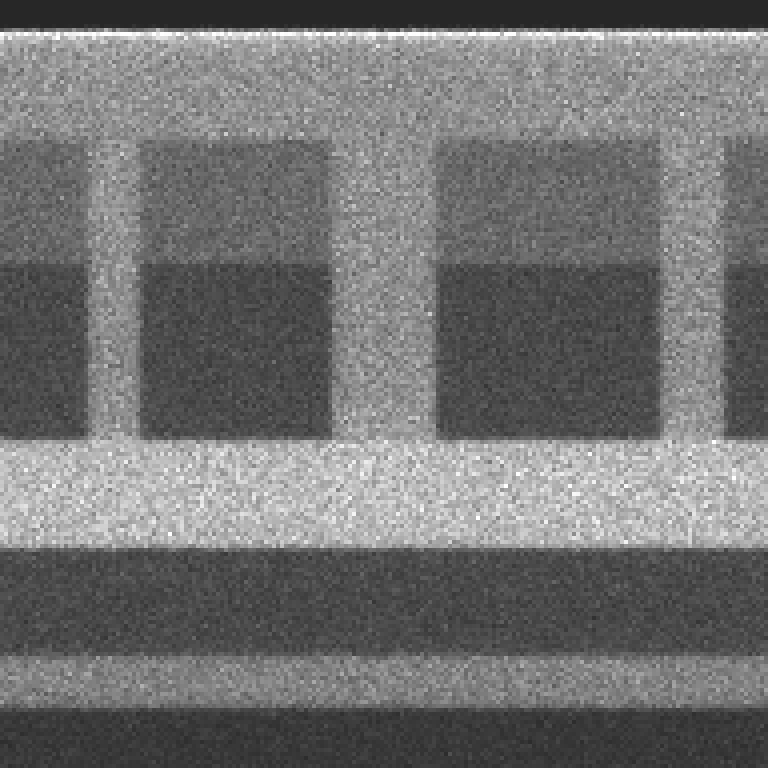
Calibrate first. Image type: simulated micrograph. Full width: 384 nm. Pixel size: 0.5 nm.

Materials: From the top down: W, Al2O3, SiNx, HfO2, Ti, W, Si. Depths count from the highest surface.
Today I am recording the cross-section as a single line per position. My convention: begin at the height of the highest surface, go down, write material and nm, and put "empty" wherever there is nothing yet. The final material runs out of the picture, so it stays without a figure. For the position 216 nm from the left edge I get W 204, HfO2 54, Ti 54, W 26, Si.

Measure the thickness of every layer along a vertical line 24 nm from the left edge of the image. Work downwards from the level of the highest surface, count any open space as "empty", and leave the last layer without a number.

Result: W 54, Al2O3 62, SiNx 88, HfO2 54, Ti 54, W 26, Si